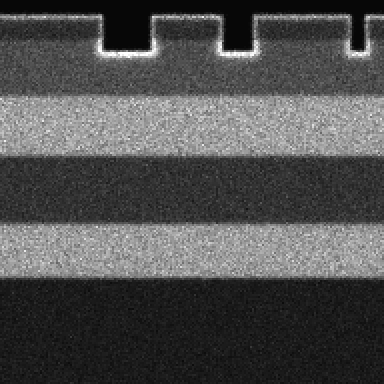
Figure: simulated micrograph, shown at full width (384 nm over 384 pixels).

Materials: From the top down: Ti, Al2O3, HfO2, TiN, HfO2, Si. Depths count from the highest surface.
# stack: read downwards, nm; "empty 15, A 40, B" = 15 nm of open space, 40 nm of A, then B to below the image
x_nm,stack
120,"empty 36, Al2O3 44, HfO2 60, TiN 68, HfO2 54, Si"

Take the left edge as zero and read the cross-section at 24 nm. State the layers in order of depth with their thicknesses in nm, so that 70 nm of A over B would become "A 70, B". Ti 24, Al2O3 56, HfO2 60, TiN 68, HfO2 54, Si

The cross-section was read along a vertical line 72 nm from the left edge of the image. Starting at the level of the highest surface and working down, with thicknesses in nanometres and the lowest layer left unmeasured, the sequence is Ti 24, Al2O3 56, HfO2 60, TiN 68, HfO2 54, Si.